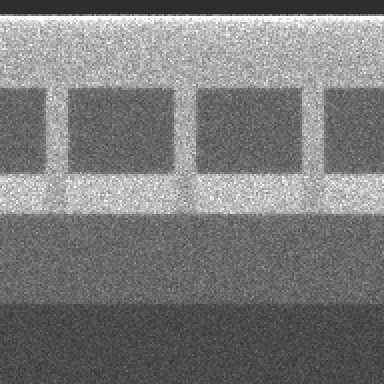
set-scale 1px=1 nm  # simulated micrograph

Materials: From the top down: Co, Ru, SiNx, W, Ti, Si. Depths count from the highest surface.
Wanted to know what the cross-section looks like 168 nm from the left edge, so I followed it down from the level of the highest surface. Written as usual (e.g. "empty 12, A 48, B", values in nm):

Co 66, Ru 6, SiNx 86, W 40, Ti 90, Si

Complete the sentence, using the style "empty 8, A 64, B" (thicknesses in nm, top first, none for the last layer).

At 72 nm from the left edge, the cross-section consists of Co 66, Ru 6, SiNx 86, W 40, Ti 90, Si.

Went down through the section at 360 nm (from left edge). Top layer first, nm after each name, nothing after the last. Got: Co 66, Ru 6, SiNx 86, W 40, Ti 90, Si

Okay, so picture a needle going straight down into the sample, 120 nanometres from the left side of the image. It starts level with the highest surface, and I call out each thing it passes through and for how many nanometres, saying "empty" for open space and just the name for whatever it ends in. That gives Co 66, Ru 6, SiNx 86, W 40, Ti 90, Si